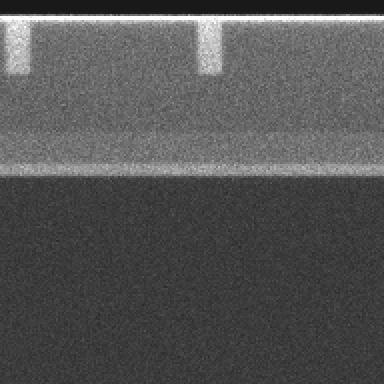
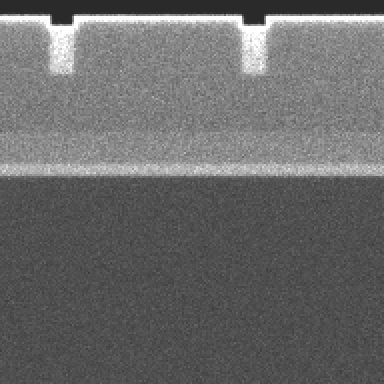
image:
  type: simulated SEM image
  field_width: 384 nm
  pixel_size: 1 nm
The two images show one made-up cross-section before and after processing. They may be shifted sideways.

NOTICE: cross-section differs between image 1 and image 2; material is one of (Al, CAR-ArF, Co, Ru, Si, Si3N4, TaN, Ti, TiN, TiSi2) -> removed: Ru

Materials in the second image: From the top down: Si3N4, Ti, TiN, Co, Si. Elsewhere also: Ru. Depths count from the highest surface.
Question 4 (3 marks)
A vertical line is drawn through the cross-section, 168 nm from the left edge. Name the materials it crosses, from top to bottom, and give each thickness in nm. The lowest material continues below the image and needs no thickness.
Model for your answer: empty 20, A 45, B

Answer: Si3N4 58, Ti 58, TiN 32, Co 12, Si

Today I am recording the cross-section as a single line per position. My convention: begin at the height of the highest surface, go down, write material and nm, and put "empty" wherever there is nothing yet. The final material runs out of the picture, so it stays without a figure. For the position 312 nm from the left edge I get Si3N4 58, Ti 58, TiN 32, Co 12, Si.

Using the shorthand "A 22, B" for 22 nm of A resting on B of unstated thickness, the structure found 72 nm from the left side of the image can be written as empty 10, Ru 48, Ti 58, TiN 32, Co 12, Si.